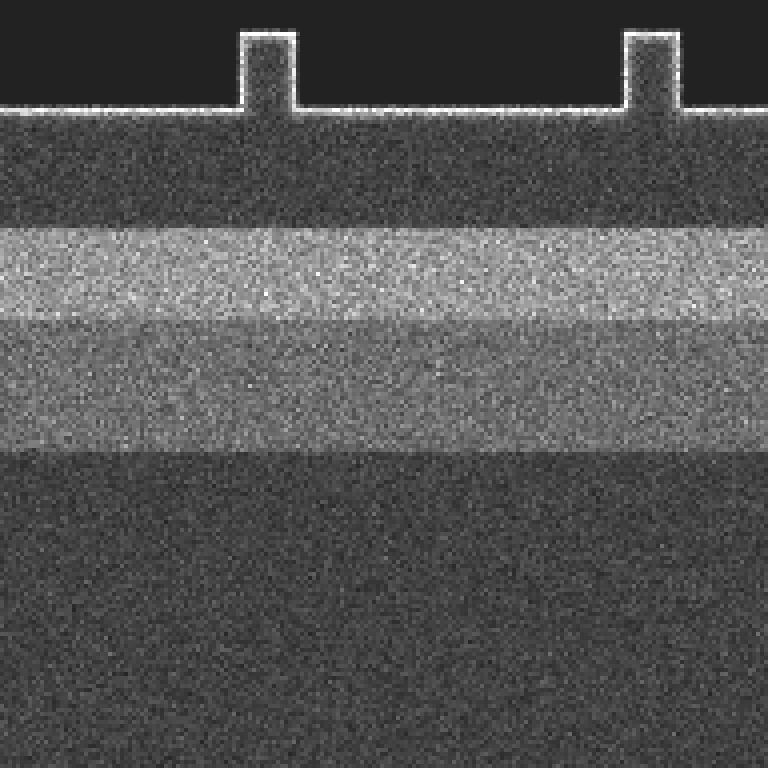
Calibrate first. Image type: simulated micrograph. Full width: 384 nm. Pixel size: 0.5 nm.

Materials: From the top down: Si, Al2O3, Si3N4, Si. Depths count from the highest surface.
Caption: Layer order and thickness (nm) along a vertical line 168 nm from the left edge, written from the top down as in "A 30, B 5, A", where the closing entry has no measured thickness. empty 38, Si 60, Al2O3 46, Si3N4 66, Si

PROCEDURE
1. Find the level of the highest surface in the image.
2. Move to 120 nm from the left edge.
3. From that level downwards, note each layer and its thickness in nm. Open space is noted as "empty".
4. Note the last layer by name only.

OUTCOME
Si 98, Al2O3 46, Si3N4 66, Si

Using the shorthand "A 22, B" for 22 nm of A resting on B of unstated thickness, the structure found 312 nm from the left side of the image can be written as Si 98, Al2O3 46, Si3N4 66, Si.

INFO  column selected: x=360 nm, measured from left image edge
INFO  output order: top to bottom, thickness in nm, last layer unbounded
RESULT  empty 38, Si 60, Al2O3 46, Si3N4 66, Si